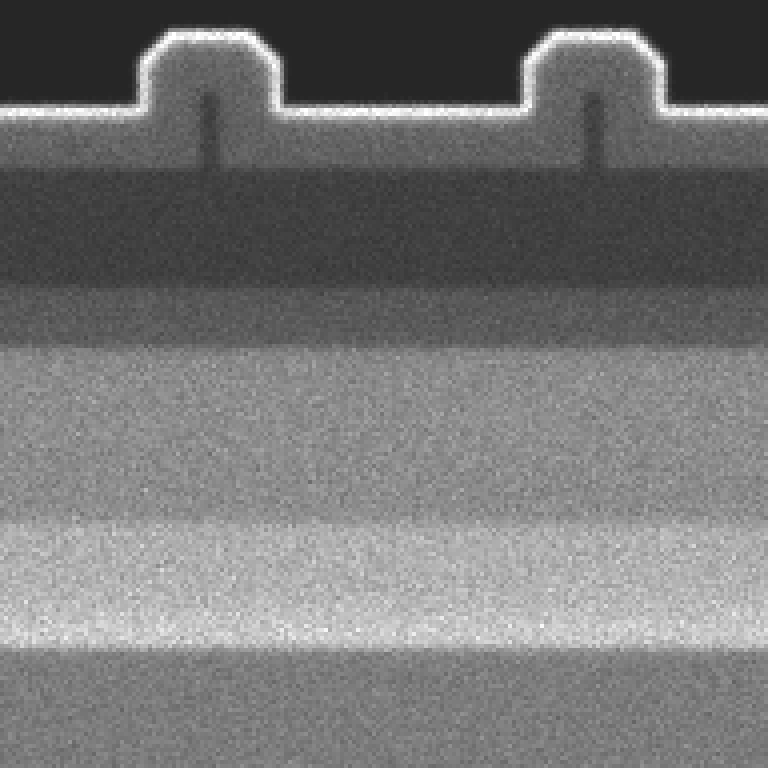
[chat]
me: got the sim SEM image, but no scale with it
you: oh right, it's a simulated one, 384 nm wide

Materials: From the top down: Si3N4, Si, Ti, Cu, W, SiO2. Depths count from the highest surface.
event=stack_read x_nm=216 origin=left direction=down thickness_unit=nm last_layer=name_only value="empty 38, Si3N4 30, Si 60, Ti 30, Cu 88, W 62, SiO2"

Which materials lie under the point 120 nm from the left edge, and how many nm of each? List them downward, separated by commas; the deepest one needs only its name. Si3N4 68, Si 60, Ti 30, Cu 88, W 62, SiO2